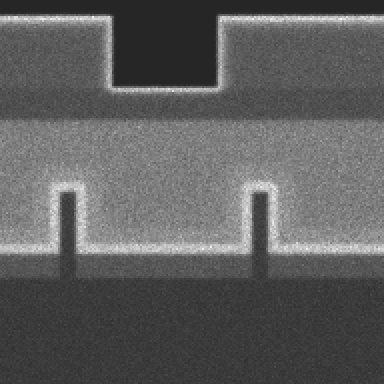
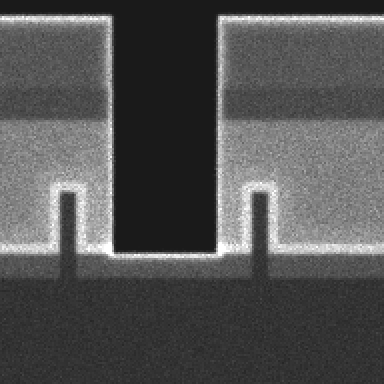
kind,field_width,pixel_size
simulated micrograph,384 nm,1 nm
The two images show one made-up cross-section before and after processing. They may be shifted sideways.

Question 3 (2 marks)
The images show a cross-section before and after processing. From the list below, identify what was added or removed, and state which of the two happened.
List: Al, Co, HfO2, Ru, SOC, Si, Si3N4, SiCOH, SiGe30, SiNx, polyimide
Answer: Co and HfO2 and Ru and SiNx was removed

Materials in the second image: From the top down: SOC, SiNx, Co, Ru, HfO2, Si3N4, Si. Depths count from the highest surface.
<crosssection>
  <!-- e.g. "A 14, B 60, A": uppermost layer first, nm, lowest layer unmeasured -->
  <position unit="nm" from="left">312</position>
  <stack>SOC 72, SiNx 32, Co 108, Ru 16, HfO2 10, Si3N4 24, Si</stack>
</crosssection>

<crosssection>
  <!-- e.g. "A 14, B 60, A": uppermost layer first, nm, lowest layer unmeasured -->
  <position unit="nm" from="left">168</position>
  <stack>empty 238, Si3N4 24, Si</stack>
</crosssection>